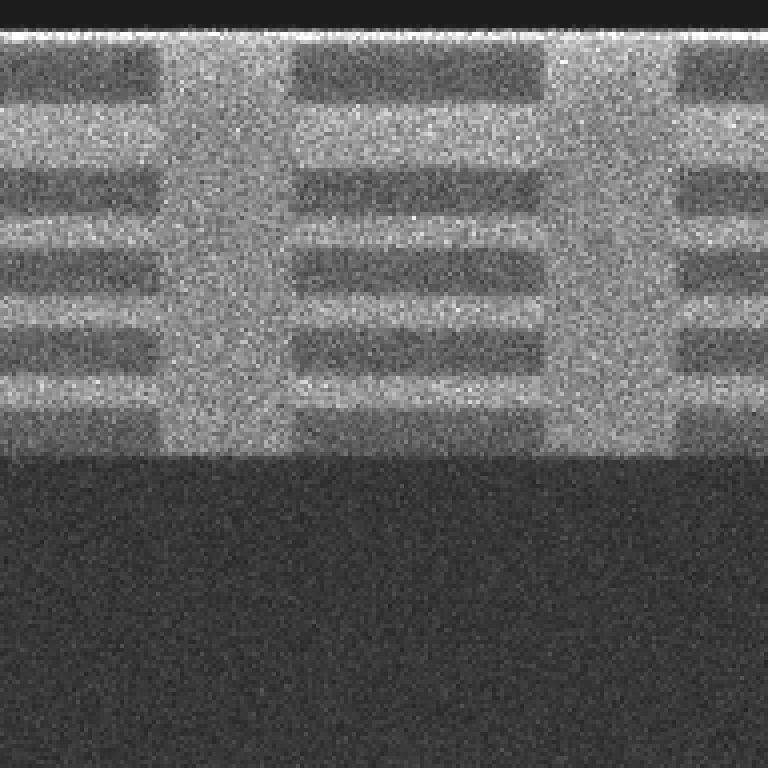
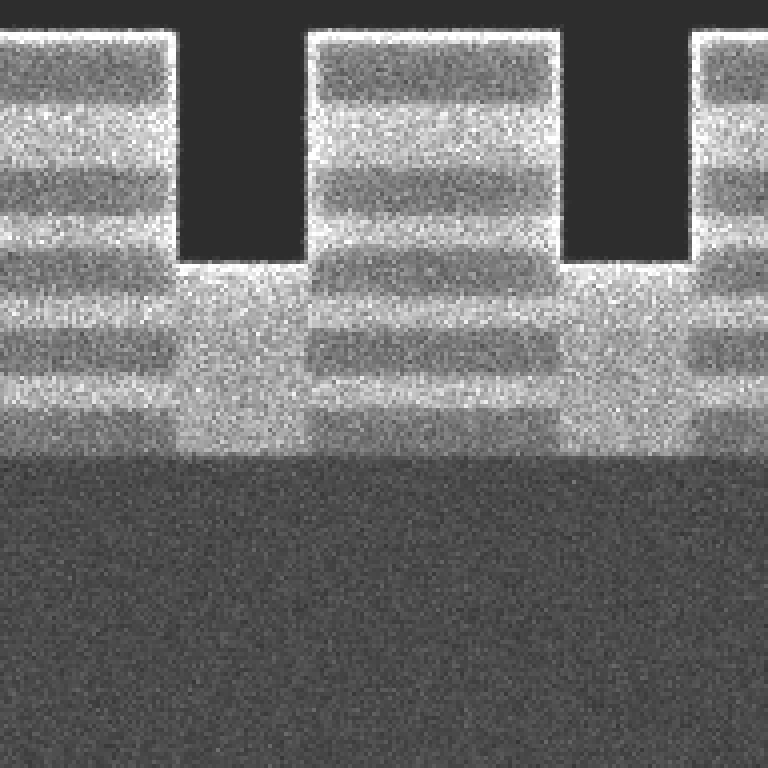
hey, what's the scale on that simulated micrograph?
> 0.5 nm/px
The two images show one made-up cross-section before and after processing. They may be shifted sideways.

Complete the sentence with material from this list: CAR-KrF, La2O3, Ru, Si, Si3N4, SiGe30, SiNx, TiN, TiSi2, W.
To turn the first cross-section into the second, Ru must be removed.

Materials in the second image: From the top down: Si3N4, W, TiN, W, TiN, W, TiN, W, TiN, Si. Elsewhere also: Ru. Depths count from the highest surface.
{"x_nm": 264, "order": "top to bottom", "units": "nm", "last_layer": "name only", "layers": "Si3N4 36, W 32, TiN 24, W 16, TiN 24, W 16, TiN 24, W 16, TiN 24, Si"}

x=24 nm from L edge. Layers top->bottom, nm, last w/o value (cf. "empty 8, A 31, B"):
Si3N4 36, W 32, TiN 24, W 16, TiN 24, W 16, TiN 24, W 16, TiN 24, Si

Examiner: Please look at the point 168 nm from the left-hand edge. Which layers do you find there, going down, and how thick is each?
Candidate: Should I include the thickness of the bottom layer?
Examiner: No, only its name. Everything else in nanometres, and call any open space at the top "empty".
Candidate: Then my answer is Si3N4 36, W 32, TiN 24, W 16, TiN 24, W 16, TiN 24, W 16, TiN 24, Si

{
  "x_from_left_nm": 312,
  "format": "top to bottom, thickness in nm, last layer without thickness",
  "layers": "empty 116, Ru 96, Si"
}